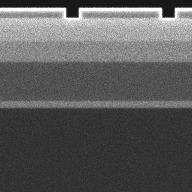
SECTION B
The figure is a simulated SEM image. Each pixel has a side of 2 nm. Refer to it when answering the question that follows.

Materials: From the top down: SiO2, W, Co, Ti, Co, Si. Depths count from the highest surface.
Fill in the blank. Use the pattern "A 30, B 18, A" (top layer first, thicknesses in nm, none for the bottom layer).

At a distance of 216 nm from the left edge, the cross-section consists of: SiO2 20, W 46, Co 42, Ti 78, Co 14, Si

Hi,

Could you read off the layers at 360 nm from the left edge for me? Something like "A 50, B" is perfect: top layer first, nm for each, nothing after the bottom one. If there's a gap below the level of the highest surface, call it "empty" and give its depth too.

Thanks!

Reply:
SiO2 20, W 46, Co 42, Ti 78, Co 14, Si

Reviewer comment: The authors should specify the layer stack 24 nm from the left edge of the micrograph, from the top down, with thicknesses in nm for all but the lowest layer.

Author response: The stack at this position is SiO2 20, W 46, Co 42, Ti 78, Co 14, Si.